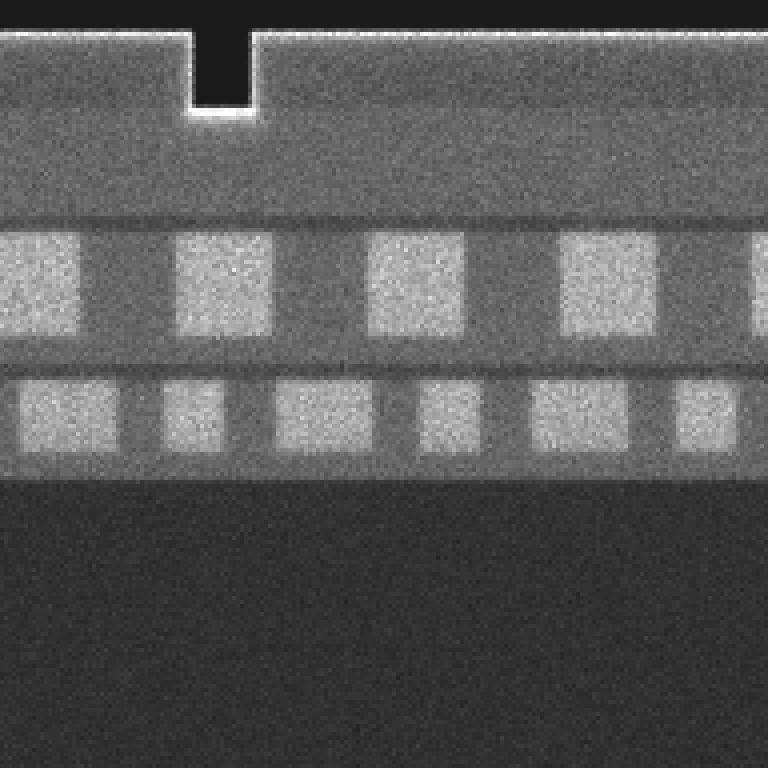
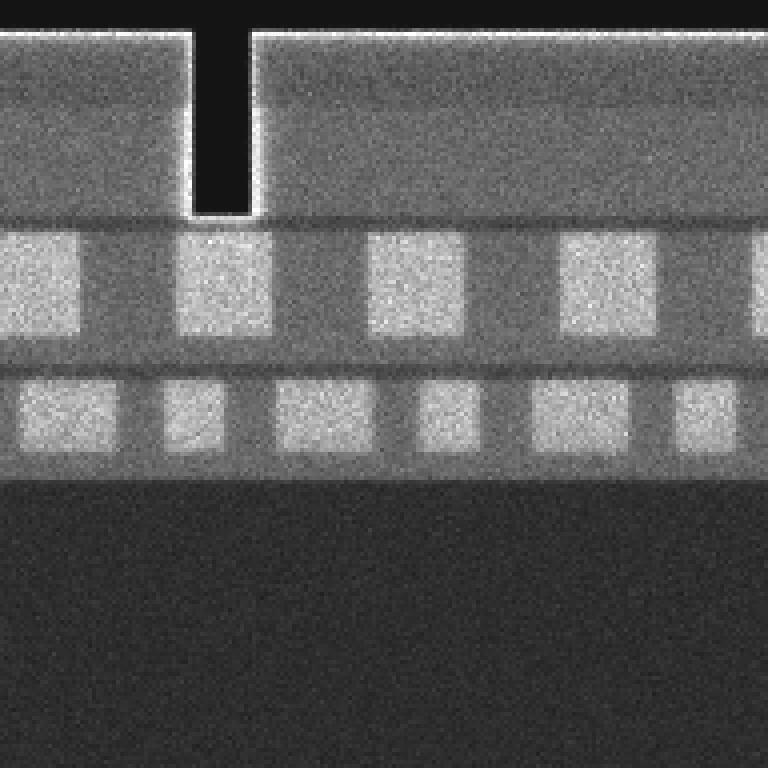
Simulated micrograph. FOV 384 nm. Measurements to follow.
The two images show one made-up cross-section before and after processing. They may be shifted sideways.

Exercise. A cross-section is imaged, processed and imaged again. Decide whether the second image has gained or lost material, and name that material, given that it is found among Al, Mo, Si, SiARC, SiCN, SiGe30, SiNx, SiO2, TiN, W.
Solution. removed: SiO2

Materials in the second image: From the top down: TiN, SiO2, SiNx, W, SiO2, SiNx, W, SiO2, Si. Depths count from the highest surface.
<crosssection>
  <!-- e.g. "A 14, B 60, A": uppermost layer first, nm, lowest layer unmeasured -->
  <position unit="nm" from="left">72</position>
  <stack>TiN 38, SiO2 54, SiNx 8, SiO2 66, SiNx 8, SiO2 50, Si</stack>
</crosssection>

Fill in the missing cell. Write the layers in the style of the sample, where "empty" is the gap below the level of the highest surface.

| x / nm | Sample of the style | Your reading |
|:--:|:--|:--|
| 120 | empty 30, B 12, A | empty 92, SiNx 8, W 52, SiO2 14, SiNx 8, SiO2 50, Si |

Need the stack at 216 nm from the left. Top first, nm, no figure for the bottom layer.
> TiN 38, SiO2 54, SiNx 8, W 52, SiO2 14, SiNx 8, W 36, SiO2 14, Si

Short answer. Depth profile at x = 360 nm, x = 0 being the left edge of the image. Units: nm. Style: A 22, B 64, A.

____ TiN 38, SiO2 54, SiNx 8, SiO2 66, SiNx 8, W 36, SiO2 14, Si